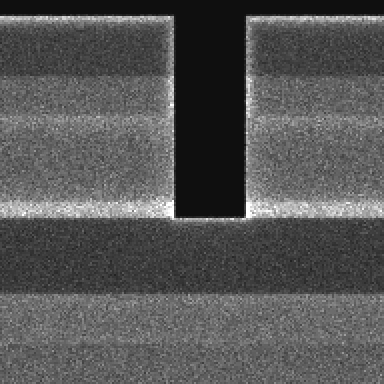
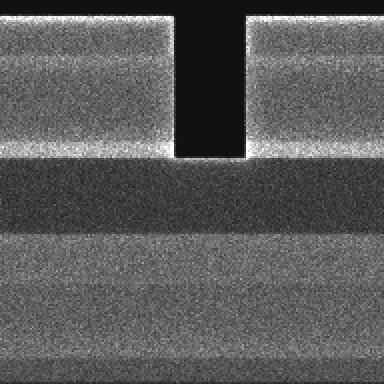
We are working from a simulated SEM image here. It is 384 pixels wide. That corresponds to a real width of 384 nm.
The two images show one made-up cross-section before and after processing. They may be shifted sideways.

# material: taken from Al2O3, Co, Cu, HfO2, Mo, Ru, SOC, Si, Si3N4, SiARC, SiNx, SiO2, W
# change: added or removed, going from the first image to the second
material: SOC
change: removed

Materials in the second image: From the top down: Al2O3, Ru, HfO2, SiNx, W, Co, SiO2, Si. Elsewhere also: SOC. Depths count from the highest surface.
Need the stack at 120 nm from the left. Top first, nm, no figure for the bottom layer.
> Al2O3 40, Ru 86, HfO2 16, SiNx 76, W 50, Co 74, SiO2 24, Si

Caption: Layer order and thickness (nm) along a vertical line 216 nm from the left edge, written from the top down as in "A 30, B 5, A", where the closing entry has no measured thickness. empty 142, SiNx 76, W 50, Co 74, SiO2 24, Si